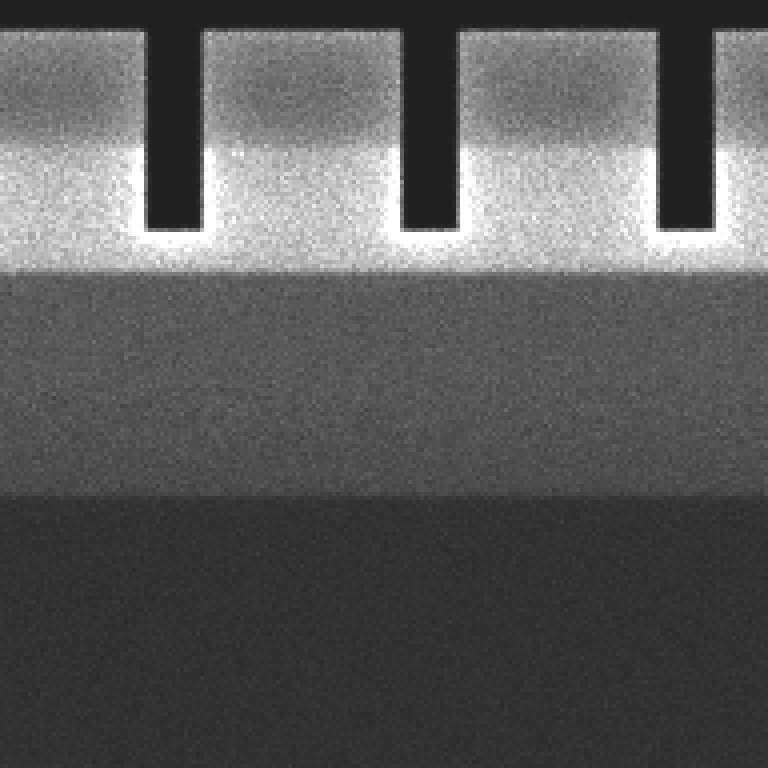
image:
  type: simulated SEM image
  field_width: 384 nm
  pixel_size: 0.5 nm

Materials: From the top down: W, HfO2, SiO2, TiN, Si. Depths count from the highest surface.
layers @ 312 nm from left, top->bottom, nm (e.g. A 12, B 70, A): W 58, HfO2 62, SiO2 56, TiN 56, Si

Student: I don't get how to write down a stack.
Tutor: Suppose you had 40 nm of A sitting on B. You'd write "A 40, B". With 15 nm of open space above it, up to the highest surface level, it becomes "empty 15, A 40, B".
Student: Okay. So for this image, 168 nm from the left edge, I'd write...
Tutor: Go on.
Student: W 58, HfO2 62, SiO2 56, TiN 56, Si